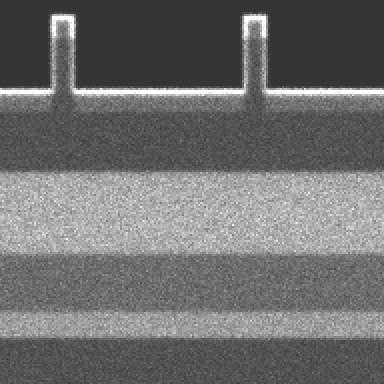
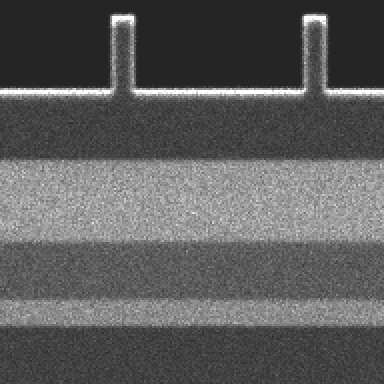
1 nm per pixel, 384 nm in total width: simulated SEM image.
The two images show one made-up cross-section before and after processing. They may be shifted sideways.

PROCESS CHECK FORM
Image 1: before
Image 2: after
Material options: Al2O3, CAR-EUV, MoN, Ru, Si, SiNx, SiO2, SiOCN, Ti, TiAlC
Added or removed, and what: removed, SiNx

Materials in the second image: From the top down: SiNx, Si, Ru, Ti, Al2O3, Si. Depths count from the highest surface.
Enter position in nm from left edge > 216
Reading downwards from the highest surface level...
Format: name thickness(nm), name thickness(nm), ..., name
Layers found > empty 74, SiNx 10, Si 60, Ru 82, Ti 58, Al2O3 26, Si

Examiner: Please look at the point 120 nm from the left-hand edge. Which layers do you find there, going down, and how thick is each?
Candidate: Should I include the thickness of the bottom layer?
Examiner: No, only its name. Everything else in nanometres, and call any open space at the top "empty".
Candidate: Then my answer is SiNx 10, Si 134, Ru 82, Ti 58, Al2O3 26, Si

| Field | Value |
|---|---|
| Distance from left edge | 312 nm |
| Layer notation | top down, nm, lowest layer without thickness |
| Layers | SiNx 10, Si 134, Ru 82, Ti 58, Al2O3 26, Si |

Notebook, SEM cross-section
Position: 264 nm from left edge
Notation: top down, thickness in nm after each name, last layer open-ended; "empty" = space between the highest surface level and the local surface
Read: empty 74, SiNx 10, Si 60, Ru 82, Ti 58, Al2O3 26, Si